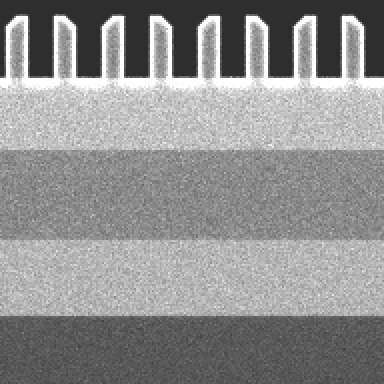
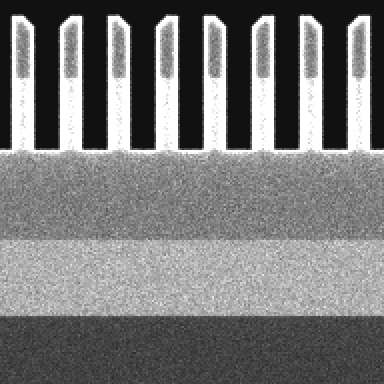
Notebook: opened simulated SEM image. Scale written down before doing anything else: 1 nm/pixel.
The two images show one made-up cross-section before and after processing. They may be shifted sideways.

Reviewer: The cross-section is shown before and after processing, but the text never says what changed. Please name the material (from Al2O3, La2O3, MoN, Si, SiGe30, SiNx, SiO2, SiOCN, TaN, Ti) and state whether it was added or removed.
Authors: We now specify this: Al2O3, removed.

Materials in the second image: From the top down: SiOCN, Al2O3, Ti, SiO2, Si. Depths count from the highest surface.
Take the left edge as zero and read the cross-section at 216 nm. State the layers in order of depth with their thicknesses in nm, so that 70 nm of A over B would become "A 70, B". empty 2, SiOCN 60, Al2O3 72, Ti 90, SiO2 76, Si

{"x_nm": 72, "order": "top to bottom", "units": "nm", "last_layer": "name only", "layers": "SiOCN 62, Al2O3 72, Ti 90, SiO2 76, Si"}